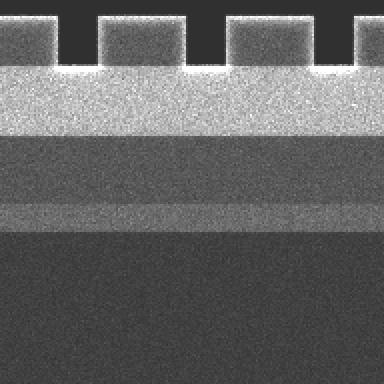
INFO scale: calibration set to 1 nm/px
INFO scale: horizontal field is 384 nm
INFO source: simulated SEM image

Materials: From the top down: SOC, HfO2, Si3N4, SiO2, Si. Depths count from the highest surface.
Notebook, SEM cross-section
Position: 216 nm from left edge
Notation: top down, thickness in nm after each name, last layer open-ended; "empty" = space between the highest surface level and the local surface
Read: empty 50, HfO2 70, Si3N4 68, SiO2 28, Si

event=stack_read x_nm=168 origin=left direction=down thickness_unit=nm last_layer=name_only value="SOC 50, HfO2 70, Si3N4 68, SiO2 28, Si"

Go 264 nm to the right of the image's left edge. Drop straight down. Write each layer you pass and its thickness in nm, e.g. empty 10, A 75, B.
SOC 50, HfO2 70, Si3N4 68, SiO2 28, Si